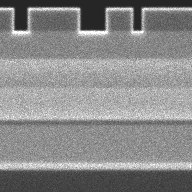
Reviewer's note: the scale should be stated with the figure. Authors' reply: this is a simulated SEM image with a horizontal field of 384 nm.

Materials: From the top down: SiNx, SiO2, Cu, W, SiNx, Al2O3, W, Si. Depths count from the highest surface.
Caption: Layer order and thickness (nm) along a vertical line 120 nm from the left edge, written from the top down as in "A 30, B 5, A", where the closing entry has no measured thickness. SiNx 46, SiO2 56, Cu 58, W 64, SiNx 10, Al2O3 76, W 14, Si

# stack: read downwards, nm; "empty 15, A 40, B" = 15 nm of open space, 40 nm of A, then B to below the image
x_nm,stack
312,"SiNx 46, SiO2 56, Cu 58, W 64, SiNx 10, Al2O3 76, W 14, Si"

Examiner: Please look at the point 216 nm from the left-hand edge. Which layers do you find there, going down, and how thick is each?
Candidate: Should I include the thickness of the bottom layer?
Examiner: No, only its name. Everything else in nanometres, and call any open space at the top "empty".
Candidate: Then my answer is SiNx 46, SiO2 56, Cu 58, W 64, SiNx 10, Al2O3 76, W 14, Si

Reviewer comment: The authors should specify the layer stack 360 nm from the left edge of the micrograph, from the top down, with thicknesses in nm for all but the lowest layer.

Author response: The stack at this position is SiNx 46, SiO2 56, Cu 58, W 64, SiNx 10, Al2O3 76, W 14, Si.